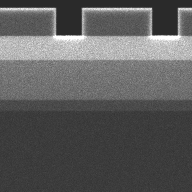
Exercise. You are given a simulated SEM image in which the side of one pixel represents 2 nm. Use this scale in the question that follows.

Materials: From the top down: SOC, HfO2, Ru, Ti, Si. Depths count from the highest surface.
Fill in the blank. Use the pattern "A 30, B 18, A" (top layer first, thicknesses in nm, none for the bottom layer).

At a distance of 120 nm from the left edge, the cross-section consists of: empty 56, HfO2 48, Ru 80, Ti 22, Si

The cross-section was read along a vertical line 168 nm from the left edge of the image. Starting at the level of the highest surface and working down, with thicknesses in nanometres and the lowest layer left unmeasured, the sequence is SOC 56, HfO2 48, Ru 80, Ti 22, Si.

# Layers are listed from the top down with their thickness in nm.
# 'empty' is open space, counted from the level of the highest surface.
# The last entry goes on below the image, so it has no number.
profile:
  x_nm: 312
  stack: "empty 56, HfO2 48, Ru 80, Ti 22, Si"